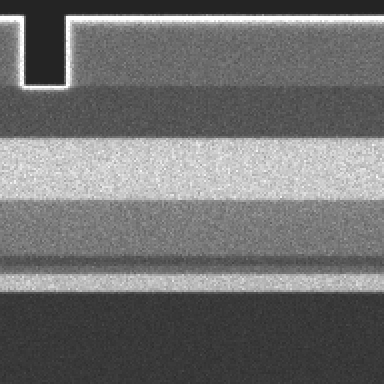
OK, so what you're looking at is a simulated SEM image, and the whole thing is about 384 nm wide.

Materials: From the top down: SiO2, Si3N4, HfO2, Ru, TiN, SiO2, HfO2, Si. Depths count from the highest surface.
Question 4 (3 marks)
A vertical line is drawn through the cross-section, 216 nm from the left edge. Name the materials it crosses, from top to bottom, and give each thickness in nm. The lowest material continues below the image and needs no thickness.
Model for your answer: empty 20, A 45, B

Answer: SiO2 70, Si3N4 52, HfO2 62, Ru 56, TiN 10, SiO2 8, HfO2 18, Si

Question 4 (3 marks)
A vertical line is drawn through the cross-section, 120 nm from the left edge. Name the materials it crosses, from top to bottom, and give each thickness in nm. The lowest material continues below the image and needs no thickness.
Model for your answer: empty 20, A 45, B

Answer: SiO2 70, Si3N4 52, HfO2 62, Ru 56, TiN 10, SiO2 8, HfO2 18, Si